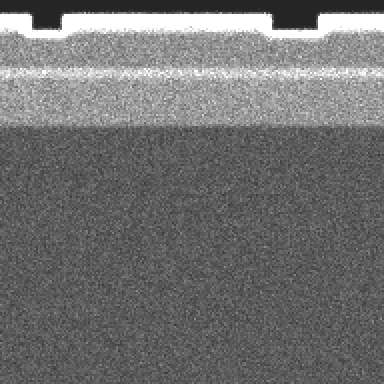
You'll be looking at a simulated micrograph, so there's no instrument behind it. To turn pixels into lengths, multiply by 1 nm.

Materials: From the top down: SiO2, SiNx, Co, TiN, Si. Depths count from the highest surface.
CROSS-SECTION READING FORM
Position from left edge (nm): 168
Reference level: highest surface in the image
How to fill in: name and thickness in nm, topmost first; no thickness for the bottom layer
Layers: SiO2 16, SiNx 36, Co 10, TiN 48, Si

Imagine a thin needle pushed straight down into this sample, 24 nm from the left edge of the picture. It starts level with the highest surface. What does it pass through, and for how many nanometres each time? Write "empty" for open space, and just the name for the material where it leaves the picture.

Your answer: SiO2 16, SiNx 36, Co 10, TiN 48, Si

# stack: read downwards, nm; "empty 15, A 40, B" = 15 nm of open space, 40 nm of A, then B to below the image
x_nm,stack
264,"SiO2 16, SiNx 36, Co 10, TiN 48, Si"